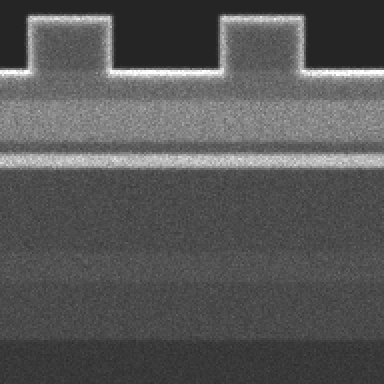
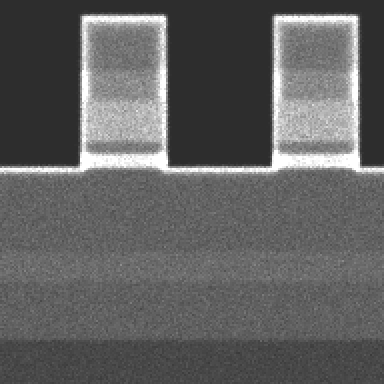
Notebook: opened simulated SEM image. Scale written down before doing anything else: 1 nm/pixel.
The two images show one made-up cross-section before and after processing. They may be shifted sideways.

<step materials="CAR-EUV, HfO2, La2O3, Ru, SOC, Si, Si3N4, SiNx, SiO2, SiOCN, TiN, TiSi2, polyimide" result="removed HfO2 and Ru and SiO2 and TiN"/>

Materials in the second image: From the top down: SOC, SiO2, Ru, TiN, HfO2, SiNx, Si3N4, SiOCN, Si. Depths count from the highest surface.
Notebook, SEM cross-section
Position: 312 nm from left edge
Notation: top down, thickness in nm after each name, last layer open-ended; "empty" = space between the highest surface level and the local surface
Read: SOC 54, SiO2 30, Ru 42, TiN 12, HfO2 14, SiNx 84, Si3N4 30, SiOCN 58, Si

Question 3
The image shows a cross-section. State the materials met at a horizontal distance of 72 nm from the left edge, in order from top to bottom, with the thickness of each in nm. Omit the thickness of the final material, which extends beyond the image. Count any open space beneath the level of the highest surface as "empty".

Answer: empty 152, SiNx 84, Si3N4 30, SiOCN 58, Si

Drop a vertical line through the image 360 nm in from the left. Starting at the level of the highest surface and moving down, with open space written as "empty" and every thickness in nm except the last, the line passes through empty 152, SiNx 84, Si3N4 30, SiOCN 58, Si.